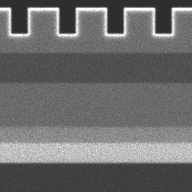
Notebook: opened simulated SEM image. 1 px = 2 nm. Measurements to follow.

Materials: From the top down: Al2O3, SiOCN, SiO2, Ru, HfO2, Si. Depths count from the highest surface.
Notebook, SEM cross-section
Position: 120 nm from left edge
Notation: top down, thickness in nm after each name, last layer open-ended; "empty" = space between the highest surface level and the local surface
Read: empty 52, Al2O3 38, SiOCN 60, SiO2 88, Ru 32, HfO2 40, Si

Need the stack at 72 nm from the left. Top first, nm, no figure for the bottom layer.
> Al2O3 90, SiOCN 60, SiO2 88, Ru 32, HfO2 40, Si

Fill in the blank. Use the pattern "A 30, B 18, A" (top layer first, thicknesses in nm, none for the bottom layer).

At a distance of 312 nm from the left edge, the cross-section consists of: empty 52, Al2O3 38, SiOCN 60, SiO2 88, Ru 32, HfO2 40, Si